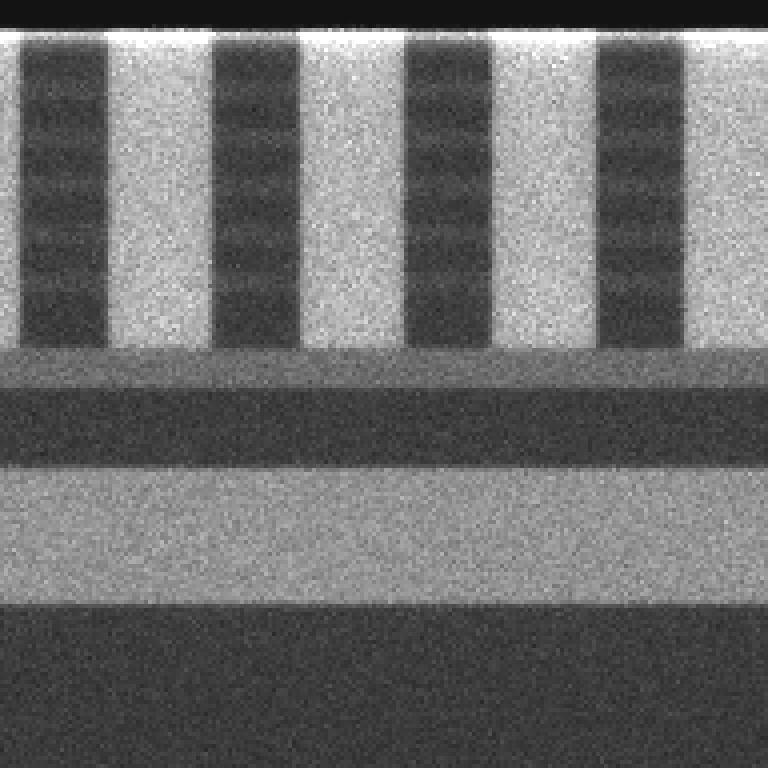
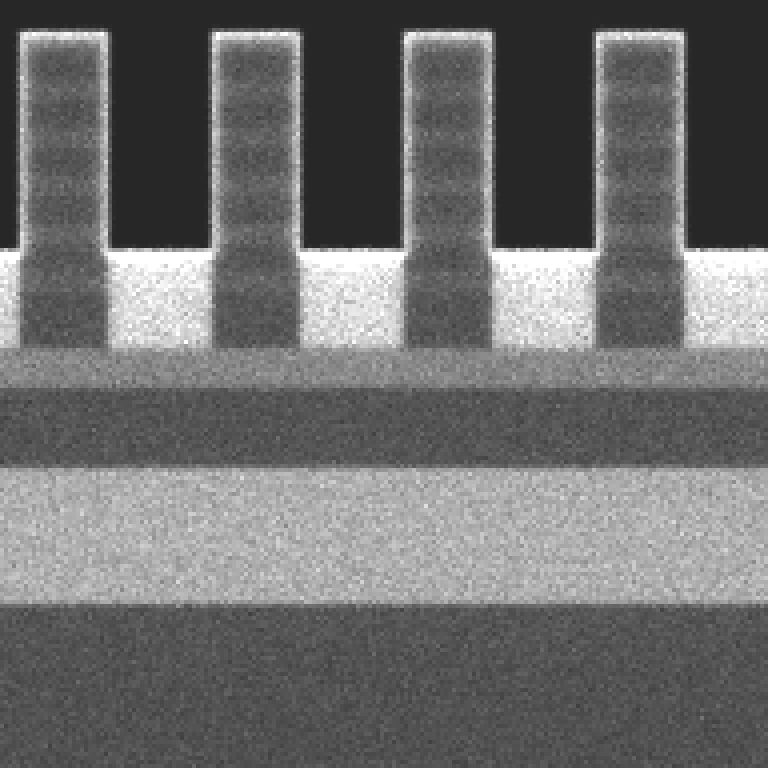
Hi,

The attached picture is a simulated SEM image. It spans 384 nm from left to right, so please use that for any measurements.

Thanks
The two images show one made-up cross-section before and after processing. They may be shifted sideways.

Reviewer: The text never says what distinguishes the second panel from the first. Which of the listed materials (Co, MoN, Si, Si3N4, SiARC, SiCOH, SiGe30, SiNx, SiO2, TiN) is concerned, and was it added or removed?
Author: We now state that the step removed Co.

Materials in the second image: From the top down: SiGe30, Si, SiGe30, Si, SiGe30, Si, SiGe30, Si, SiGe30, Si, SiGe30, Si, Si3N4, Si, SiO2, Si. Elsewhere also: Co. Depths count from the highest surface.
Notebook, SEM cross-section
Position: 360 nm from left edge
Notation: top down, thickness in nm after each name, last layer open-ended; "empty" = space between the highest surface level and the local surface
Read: empty 110, Co 48, Si3N4 20, Si 40, SiO2 68, Si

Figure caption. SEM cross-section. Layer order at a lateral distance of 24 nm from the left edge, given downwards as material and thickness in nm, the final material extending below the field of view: SiGe30 10, Si 14, SiGe30 10, Si 14, SiGe30 10, Si 14, SiGe30 10, Si 14, SiGe30 10, Si 14, SiGe30 10, Si 28, Si3N4 20, Si 40, SiO2 68, Si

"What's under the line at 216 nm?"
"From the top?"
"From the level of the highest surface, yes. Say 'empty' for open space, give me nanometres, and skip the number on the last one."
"SiGe30 10, Si 14, SiGe30 10, Si 14, SiGe30 10, Si 14, SiGe30 10, Si 14, SiGe30 10, Si 14, SiGe30 10, Si 28, Si3N4 20, Si 40, SiO2 68, Si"